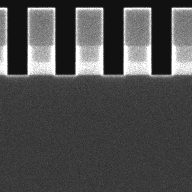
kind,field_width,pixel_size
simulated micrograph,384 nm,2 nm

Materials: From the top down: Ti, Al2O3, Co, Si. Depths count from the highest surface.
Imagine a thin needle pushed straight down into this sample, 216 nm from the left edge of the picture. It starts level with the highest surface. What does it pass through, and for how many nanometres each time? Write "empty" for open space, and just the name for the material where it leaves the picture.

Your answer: empty 134, Si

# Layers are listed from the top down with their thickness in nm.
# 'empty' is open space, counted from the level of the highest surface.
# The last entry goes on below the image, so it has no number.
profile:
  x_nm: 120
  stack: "empty 134, Si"